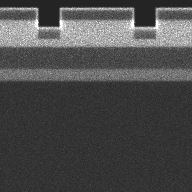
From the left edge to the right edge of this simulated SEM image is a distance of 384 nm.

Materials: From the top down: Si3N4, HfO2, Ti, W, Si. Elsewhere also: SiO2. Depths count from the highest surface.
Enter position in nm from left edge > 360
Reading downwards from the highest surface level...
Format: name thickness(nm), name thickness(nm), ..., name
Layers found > Si3N4 24, HfO2 54, Ti 44, W 24, Si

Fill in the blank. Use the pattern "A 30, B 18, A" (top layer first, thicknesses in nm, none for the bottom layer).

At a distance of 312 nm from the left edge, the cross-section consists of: Si3N4 24, HfO2 54, Ti 44, W 24, Si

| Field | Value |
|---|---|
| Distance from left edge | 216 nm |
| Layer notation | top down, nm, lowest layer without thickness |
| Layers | Si3N4 24, HfO2 54, Ti 44, W 24, Si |